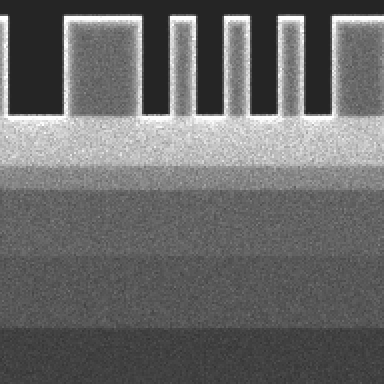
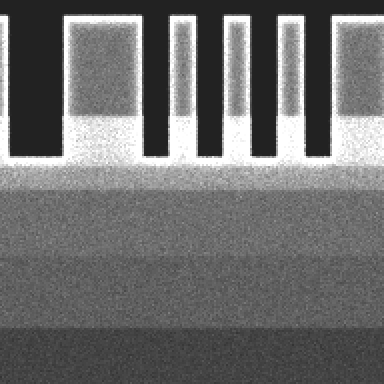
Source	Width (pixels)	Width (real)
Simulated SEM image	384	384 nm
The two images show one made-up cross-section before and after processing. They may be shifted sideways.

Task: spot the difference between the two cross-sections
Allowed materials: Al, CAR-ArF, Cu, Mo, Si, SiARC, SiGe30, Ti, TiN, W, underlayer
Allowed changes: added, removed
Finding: removed W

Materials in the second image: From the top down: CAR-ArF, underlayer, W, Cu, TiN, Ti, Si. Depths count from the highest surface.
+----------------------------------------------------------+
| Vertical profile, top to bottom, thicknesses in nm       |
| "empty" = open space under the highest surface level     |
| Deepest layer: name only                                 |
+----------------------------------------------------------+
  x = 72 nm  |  CAR-ArF 44, underlayer 56, W 50, Cu 24, TiN 66, Ti 72, Si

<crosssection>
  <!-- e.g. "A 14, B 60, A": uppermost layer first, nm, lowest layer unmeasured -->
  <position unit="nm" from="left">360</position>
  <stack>CAR-ArF 44, underlayer 56, W 50, Cu 24, TiN 66, Ti 72, Si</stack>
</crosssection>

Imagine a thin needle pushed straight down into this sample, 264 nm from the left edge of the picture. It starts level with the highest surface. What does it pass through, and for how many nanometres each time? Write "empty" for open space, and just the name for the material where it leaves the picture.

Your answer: empty 142, W 8, Cu 24, TiN 66, Ti 72, Si